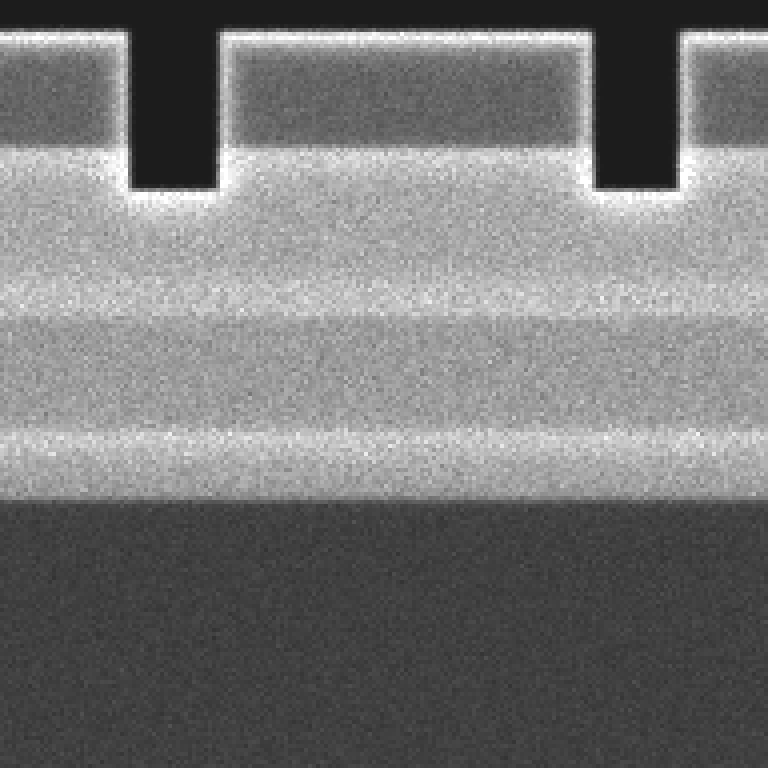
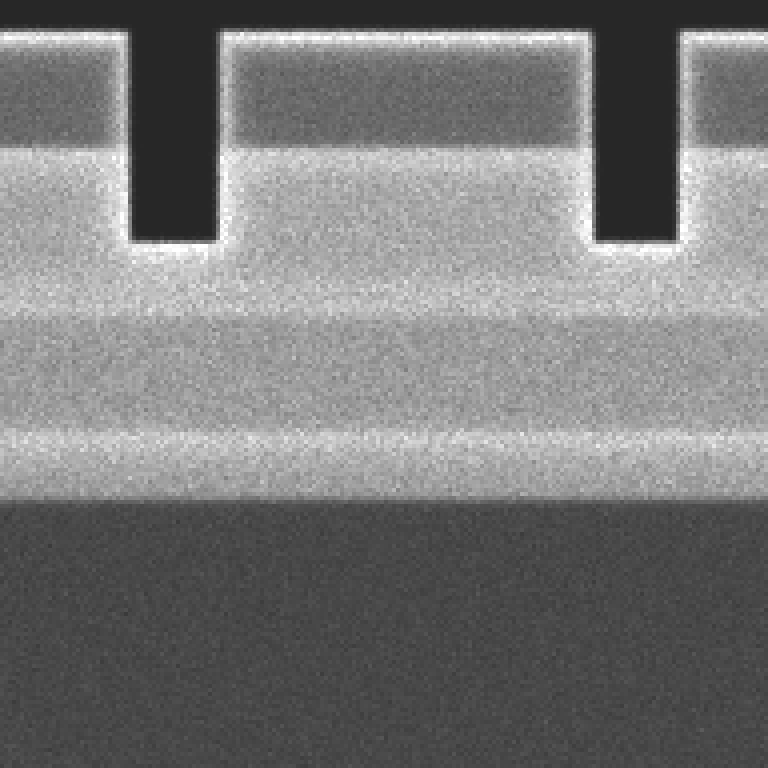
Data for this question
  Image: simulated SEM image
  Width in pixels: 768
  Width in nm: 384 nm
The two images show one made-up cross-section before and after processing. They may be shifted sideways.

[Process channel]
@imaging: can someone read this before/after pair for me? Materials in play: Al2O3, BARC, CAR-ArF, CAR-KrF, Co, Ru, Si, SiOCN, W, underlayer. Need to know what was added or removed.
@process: W removed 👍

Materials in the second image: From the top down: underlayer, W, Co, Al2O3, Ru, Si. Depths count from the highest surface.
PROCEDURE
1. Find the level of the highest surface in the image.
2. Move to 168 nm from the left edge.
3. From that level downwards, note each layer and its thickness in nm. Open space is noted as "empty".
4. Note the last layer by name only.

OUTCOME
underlayer 58, W 72, Co 12, Al2O3 58, Ru 34, Si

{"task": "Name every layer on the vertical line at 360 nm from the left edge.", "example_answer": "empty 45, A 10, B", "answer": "underlayer 58, W 72, Co 12, Al2O3 58, Ru 34, Si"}